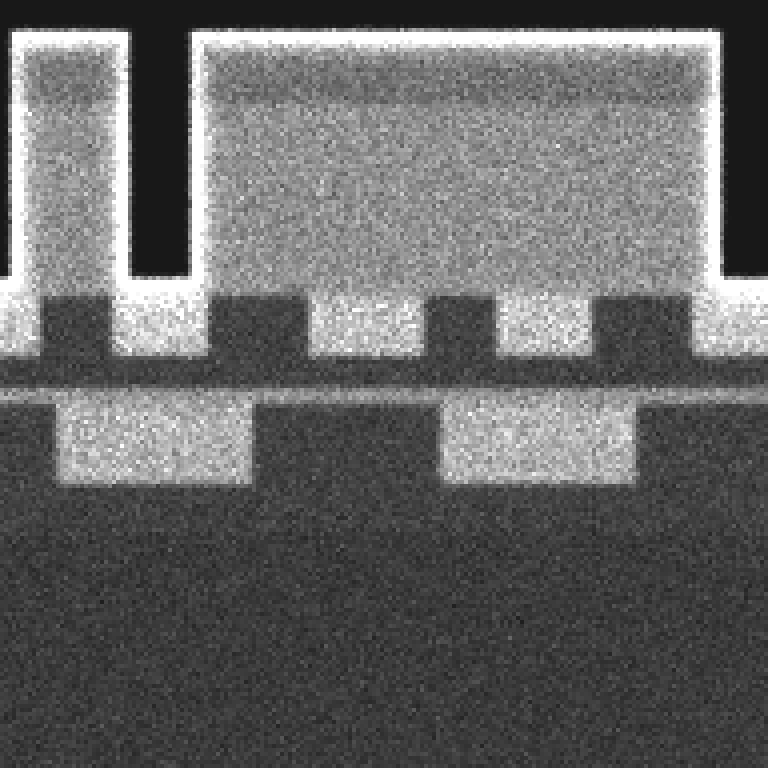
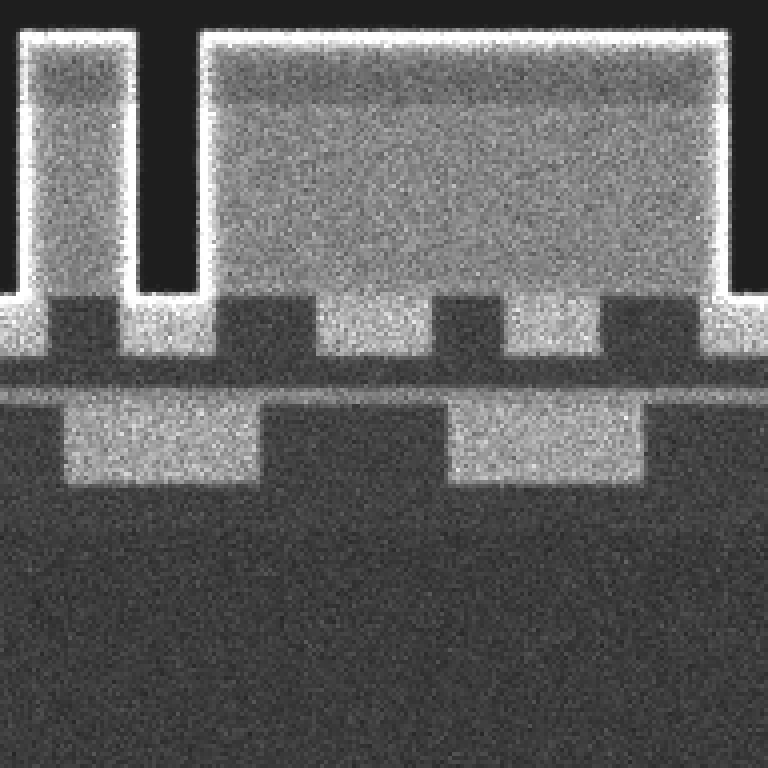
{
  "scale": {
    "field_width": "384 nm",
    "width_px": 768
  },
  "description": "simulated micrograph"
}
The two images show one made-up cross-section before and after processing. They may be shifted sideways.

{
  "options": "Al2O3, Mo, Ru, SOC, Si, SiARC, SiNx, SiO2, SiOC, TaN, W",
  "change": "removed",
  "material": "Al2O3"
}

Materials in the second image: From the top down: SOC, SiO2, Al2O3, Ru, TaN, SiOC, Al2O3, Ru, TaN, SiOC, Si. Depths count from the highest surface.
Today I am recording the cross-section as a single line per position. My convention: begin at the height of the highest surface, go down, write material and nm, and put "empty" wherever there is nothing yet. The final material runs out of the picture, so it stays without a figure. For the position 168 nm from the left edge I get SOC 36, SiO2 88, Al2O3 8, Ru 22, TaN 8, SiOC 16, Al2O3 8, SiOC 64, Si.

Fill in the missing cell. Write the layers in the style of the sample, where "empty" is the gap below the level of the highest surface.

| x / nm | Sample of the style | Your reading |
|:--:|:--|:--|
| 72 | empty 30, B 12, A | empty 132, Ru 22, TaN 8, SiOC 16, Al2O3 8, Ru 32, TaN 8, SiOC 24, Si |